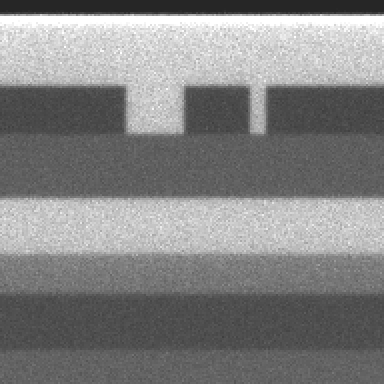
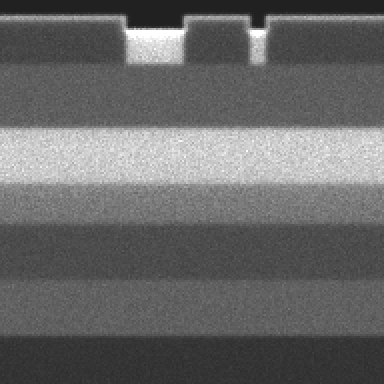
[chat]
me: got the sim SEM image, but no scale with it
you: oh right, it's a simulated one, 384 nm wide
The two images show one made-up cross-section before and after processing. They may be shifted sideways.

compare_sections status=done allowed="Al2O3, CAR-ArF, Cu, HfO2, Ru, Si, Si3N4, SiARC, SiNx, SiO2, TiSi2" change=removed material="HfO2"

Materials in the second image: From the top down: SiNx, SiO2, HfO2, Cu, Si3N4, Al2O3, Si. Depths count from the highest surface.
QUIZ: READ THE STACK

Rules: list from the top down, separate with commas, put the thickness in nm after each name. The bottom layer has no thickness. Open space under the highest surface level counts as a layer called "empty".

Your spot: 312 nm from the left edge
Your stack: SiNx 48, SiO2 64, HfO2 56, Cu 40, Si3N4 56, Al2O3 56, Si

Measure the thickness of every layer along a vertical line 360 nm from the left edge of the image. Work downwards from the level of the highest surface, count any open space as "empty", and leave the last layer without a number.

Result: SiNx 48, SiO2 64, HfO2 56, Cu 40, Si3N4 56, Al2O3 56, Si